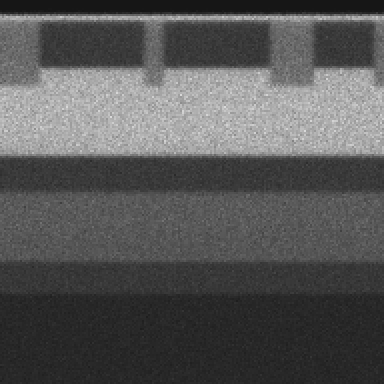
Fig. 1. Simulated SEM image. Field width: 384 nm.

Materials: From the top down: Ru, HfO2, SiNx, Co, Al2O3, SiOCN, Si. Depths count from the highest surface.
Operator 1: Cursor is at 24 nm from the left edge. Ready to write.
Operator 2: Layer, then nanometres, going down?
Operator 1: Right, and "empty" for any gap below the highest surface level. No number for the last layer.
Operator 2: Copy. Ru 70, HfO2 70, SiNx 36, Co 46, Al2O3 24, SiOCN 32, Si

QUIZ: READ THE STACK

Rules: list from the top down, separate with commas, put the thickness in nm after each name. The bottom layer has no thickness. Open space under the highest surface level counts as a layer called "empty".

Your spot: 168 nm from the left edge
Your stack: SiNx 52, HfO2 88, SiNx 36, Co 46, Al2O3 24, SiOCN 32, Si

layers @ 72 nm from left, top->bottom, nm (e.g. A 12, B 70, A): SiNx 52, HfO2 88, SiNx 36, Co 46, Al2O3 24, SiOCN 32, Si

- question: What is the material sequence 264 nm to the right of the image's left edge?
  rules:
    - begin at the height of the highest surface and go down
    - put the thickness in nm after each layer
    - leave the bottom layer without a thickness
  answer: SiNx 52, HfO2 88, SiNx 36, Co 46, Al2O3 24, SiOCN 32, Si